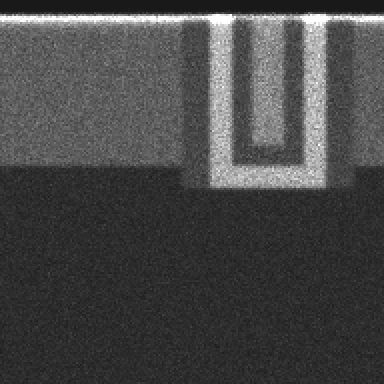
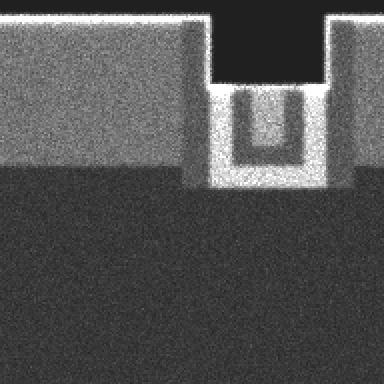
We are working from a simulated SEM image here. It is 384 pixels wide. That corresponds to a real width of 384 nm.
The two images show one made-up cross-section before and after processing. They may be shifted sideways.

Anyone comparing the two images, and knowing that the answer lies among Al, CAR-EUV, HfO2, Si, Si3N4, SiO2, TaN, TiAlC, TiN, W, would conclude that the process removed HfO2 and TiN and W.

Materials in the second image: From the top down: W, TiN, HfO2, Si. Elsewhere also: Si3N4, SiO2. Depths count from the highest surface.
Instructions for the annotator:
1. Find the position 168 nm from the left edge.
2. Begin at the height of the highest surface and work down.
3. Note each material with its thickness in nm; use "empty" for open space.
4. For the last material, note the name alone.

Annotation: SiO2 150, Si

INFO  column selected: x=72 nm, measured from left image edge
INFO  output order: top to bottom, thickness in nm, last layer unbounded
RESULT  SiO2 150, Si